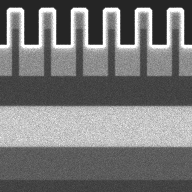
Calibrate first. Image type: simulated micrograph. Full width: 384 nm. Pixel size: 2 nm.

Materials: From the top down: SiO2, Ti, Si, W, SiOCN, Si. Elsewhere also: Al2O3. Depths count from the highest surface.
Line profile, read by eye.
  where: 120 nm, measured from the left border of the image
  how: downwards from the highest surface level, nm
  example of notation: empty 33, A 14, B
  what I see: empty 74, SiO2 10, Al2O3 52, Si 60, W 82, SiOCN 66, Si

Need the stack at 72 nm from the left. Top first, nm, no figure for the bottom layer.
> empty 74, SiO2 10, Al2O3 52, Si 60, W 82, SiOCN 66, Si